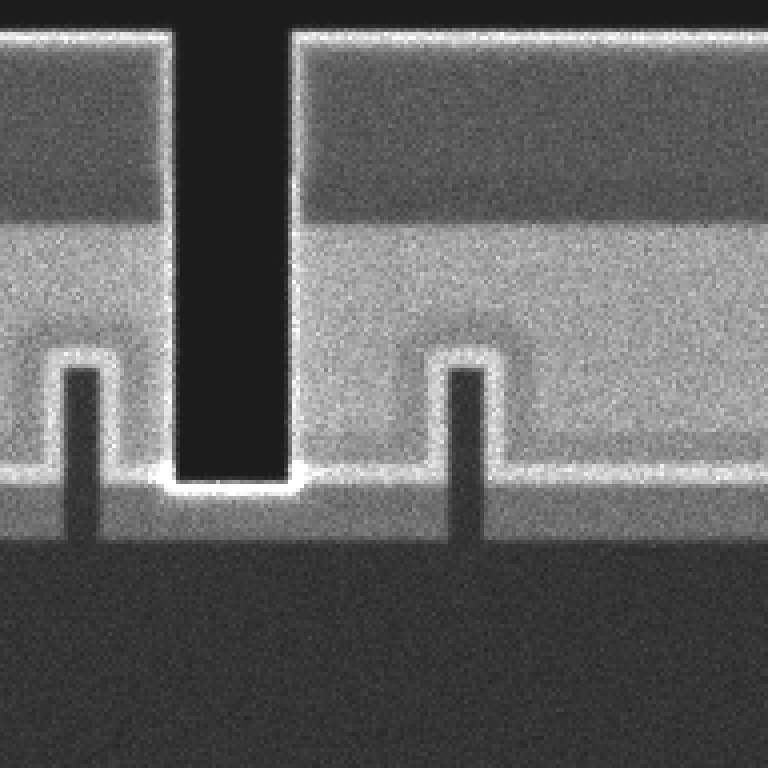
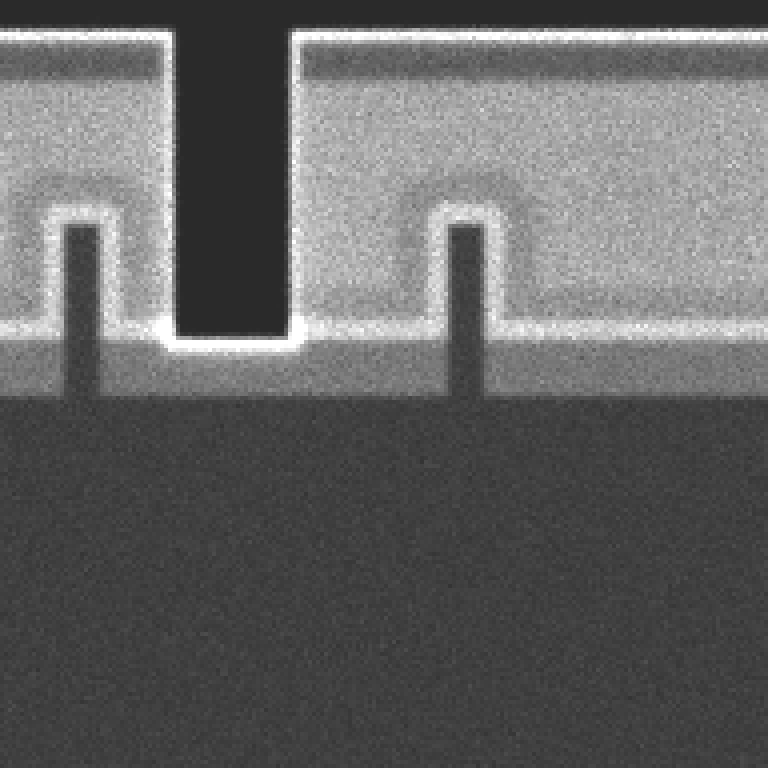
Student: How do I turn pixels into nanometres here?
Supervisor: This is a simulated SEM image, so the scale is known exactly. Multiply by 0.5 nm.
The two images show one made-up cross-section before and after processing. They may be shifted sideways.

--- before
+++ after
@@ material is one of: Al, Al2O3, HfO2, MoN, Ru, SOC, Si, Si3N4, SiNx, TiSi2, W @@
SOC removed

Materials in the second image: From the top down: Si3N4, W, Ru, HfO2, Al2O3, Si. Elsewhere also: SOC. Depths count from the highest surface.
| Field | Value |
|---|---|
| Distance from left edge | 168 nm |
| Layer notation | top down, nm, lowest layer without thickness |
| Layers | Si3N4 24, W 104, Ru 16, HfO2 10, Al2O3 28, Si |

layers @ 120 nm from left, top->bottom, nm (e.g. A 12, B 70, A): empty 154, Al2O3 28, Si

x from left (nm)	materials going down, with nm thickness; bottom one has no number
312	Si3N4 24, W 104, Ru 16, HfO2 10, Al2O3 28, Si